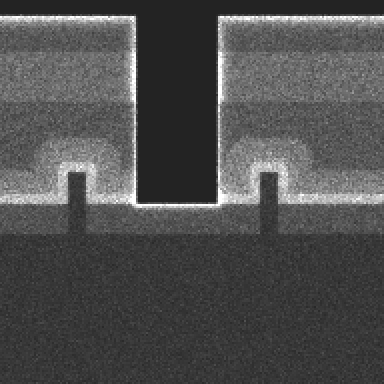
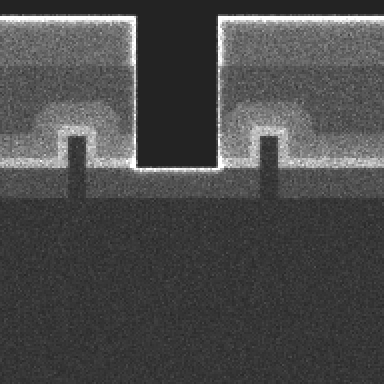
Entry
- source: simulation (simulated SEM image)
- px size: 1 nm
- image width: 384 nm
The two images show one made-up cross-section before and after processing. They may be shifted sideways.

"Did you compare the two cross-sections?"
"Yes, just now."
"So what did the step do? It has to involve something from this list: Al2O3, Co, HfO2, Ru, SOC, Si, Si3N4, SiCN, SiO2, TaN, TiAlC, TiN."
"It removed SOC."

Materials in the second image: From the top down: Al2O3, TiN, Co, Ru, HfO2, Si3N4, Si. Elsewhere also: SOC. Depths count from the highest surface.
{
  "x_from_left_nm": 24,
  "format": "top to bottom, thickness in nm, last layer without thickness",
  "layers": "Al2O3 50, TiN 68, Co 14, Ru 10, HfO2 10, Si3N4 30, Si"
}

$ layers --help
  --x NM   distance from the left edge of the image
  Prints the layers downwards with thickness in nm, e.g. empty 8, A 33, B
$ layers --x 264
Al2O3 50, TiN 36, Co 14, Ru 10, HfO2 10, Si